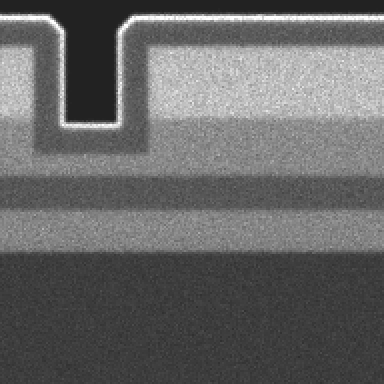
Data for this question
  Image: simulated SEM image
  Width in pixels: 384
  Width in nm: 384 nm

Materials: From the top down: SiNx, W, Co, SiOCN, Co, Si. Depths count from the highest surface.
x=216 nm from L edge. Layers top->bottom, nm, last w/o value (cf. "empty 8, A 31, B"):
SiNx 30, W 72, Co 58, SiOCN 34, Co 42, Si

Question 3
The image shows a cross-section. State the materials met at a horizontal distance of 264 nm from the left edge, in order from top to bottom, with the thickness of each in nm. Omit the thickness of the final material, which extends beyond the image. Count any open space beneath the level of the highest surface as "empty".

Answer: SiNx 30, W 72, Co 58, SiOCN 34, Co 42, Si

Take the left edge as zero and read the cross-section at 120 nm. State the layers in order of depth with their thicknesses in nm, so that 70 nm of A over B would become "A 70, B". empty 12, SiNx 126, Co 22, SiOCN 34, Co 42, Si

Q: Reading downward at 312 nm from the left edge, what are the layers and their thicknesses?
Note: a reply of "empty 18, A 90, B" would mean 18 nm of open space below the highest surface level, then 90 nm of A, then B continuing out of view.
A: SiNx 30, W 72, Co 58, SiOCN 34, Co 42, Si